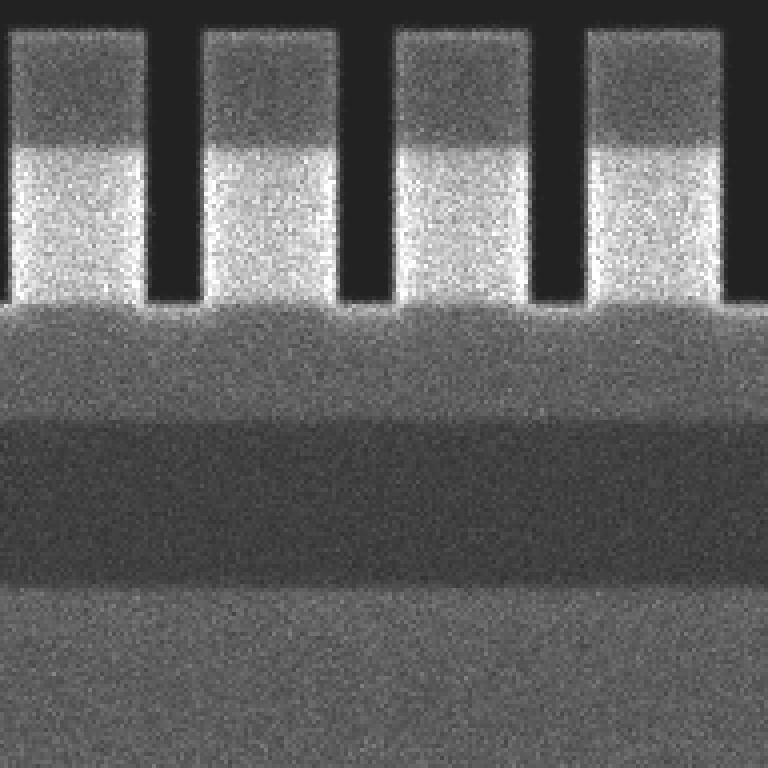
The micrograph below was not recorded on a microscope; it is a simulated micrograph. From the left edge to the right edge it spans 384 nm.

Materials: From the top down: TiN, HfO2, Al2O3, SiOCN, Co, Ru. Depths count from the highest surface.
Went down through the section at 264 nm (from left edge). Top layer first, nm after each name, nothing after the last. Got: empty 136, Al2O3 58, SiOCN 84, Co 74, Ru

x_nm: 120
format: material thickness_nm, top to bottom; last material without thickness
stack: TiN 58, HfO2 78, Al2O3 58, SiOCN 84, Co 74, Ru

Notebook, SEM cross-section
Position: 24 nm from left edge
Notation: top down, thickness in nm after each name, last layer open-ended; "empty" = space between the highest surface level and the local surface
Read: TiN 58, HfO2 78, Al2O3 58, SiOCN 84, Co 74, Ru